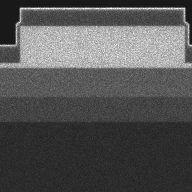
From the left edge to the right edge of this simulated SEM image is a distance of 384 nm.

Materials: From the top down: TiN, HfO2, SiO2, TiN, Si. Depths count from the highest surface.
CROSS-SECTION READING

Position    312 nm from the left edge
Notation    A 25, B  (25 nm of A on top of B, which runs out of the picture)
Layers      TiN 36, HfO2 84, SiO2 58, TiN 50, Si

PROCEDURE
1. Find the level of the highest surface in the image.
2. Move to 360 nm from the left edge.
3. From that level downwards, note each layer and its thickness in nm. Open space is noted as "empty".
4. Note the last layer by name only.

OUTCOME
TiN 36, HfO2 84, SiO2 58, TiN 50, Si